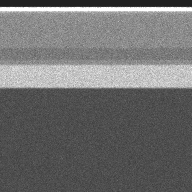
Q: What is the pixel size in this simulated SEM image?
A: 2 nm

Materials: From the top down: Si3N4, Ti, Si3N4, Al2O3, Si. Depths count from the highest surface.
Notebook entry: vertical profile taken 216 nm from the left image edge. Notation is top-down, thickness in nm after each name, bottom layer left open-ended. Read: Si3N4 80, Ti 24, Si3N4 10, Al2O3 46, Si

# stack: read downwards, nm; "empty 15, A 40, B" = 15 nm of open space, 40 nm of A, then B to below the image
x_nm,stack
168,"Si3N4 80, Ti 24, Si3N4 10, Al2O3 46, Si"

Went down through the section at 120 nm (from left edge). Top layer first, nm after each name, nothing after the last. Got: Si3N4 80, Ti 24, Si3N4 10, Al2O3 46, Si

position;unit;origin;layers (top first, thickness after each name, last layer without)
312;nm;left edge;Si3N4 80, Ti 24, Si3N4 10, Al2O3 46, Si